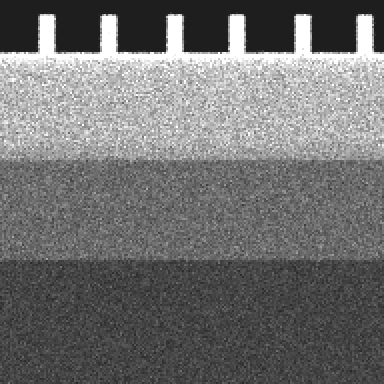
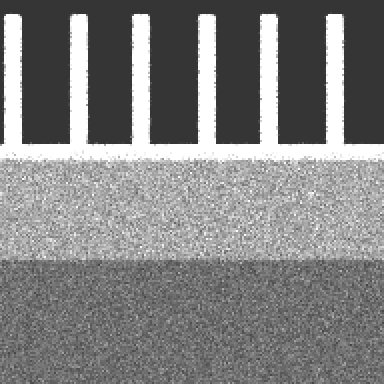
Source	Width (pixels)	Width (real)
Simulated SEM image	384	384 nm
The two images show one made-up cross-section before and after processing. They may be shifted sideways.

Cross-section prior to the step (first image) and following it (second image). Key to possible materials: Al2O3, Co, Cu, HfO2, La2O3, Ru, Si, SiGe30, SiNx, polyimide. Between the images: Ru was removed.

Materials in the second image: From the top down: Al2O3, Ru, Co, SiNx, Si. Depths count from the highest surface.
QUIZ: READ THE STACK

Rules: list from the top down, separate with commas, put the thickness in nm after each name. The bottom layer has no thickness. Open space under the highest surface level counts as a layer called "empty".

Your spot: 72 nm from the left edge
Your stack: Al2O3 38, Ru 92, Co 14, SiNx 100, Si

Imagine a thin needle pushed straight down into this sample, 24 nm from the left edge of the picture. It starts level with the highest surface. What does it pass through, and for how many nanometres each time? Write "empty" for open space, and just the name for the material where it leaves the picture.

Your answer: empty 130, Co 14, SiNx 100, Si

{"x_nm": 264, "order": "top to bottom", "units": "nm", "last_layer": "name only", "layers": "Al2O3 38, Ru 92, Co 14, SiNx 100, Si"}